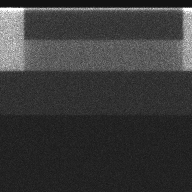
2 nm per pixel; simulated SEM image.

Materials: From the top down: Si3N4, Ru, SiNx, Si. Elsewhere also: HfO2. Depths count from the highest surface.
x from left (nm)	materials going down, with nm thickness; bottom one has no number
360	Si3N4 64, Ru 62, SiNx 88, Si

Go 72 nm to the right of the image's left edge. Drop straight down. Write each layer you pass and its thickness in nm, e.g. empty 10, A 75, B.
Si3N4 64, Ru 62, SiNx 88, Si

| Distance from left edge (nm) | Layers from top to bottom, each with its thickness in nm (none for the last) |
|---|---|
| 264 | Si3N4 64, Ru 62, SiNx 88, Si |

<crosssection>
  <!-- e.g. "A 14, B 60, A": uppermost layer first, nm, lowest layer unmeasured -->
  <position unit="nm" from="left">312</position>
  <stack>Si3N4 64, Ru 62, SiNx 88, Si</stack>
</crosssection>